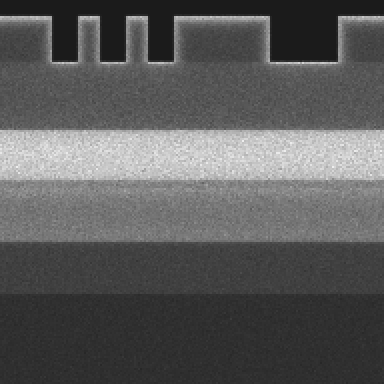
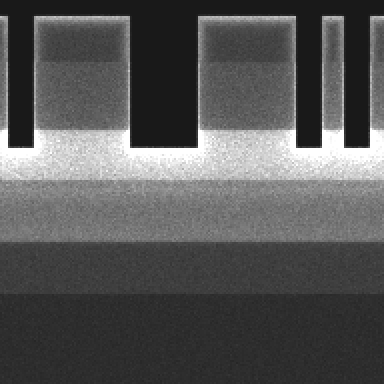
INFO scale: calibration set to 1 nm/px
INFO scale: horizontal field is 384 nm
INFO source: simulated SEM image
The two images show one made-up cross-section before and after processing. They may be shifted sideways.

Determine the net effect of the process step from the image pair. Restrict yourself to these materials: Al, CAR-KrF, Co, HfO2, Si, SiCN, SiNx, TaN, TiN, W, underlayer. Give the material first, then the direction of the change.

HfO2 and TiN: removed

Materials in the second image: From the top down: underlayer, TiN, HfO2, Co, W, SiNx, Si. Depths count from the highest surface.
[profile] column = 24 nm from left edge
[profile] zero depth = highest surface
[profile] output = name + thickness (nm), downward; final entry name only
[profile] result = empty 132, HfO2 32, Co 8, W 54, SiNx 52, Si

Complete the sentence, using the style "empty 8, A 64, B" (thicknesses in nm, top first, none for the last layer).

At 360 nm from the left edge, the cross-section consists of empty 132, HfO2 32, Co 8, W 54, SiNx 52, Si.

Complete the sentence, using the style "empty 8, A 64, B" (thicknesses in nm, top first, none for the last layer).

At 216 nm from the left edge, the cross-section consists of underlayer 46, TiN 68, HfO2 50, Co 8, W 54, SiNx 52, Si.